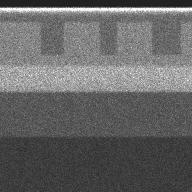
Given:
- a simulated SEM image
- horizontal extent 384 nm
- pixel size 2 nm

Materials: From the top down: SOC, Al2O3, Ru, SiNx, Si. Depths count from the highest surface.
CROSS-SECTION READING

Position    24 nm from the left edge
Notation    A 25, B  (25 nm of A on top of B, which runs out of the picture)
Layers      SOC 28, Al2O3 88, Ru 52, SiNx 90, Si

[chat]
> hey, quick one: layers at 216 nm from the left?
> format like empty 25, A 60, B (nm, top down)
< SOC 94, Al2O3 22, Ru 52, SiNx 90, Si